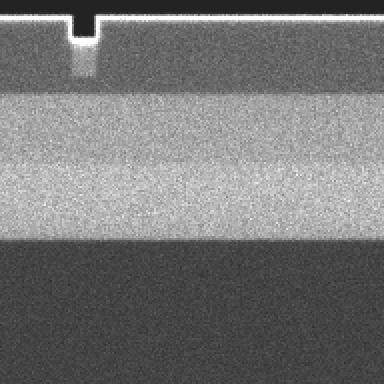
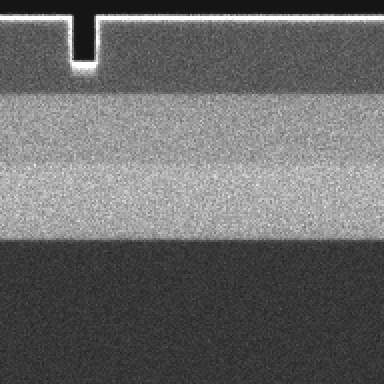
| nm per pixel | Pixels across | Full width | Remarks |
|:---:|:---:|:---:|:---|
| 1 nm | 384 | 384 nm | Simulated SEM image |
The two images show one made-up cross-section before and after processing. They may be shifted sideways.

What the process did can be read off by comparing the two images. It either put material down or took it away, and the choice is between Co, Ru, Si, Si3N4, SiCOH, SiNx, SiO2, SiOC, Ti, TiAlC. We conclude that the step removed SiO2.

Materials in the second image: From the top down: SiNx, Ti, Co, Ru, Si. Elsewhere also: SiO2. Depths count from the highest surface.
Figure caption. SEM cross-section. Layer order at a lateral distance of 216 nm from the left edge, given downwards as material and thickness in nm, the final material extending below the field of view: SiNx 30, Ti 48, Co 70, Ru 76, Si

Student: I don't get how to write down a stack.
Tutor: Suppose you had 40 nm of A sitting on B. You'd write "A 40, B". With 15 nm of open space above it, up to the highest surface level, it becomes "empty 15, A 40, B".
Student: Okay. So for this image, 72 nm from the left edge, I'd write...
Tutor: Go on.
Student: empty 46, SiO2 14, Ti 18, Co 70, Ru 76, Si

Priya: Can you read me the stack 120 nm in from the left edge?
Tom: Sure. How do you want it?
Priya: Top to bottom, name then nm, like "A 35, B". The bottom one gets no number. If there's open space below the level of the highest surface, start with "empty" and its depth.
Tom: SiNx 30, Ti 48, Co 70, Ru 76, Si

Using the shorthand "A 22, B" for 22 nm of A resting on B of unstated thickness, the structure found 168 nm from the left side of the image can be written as SiNx 30, Ti 48, Co 70, Ru 76, Si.